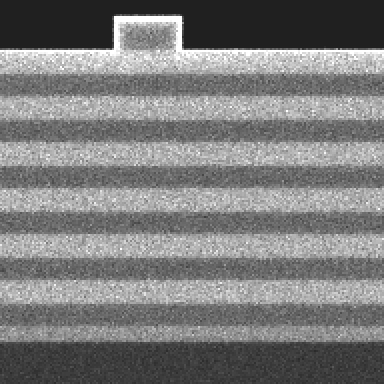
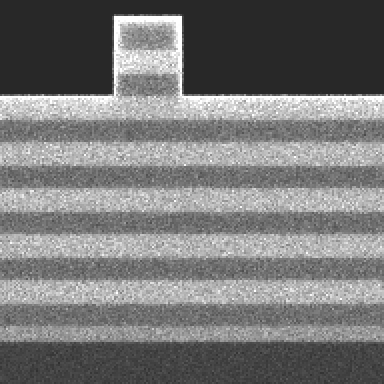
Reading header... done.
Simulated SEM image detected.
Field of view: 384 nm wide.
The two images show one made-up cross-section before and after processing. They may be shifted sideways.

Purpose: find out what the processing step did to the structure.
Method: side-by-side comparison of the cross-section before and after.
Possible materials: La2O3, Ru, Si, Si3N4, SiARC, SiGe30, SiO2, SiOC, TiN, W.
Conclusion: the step removed TiN and W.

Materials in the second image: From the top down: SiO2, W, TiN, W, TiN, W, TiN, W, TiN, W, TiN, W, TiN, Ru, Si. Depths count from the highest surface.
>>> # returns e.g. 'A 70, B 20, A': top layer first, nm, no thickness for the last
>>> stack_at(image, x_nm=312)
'empty 80, W 24, TiN 22, W 24, TiN 22, W 24, TiN 22, W 24, TiN 22, W 24, TiN 22, Ru 16, Si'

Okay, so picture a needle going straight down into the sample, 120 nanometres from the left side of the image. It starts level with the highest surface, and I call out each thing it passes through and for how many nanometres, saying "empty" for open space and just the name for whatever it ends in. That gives SiO2 34, W 24, TiN 22, W 24, TiN 22, W 24, TiN 22, W 24, TiN 22, W 24, TiN 22, W 24, TiN 22, Ru 16, Si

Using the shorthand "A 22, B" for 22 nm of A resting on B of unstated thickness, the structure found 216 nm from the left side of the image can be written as empty 80, W 24, TiN 22, W 24, TiN 22, W 24, TiN 22, W 24, TiN 22, W 24, TiN 22, Ru 16, Si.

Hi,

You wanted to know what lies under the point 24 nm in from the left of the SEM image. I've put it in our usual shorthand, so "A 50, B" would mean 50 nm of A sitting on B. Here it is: empty 80, W 24, TiN 22, W 24, TiN 22, W 24, TiN 22, W 24, TiN 22, W 24, TiN 22, Ru 16, Si